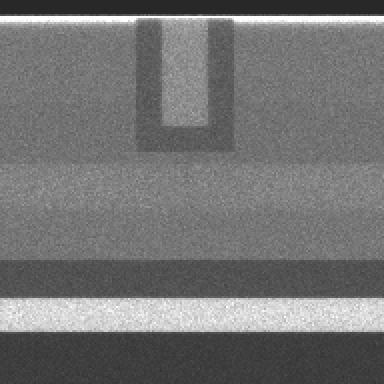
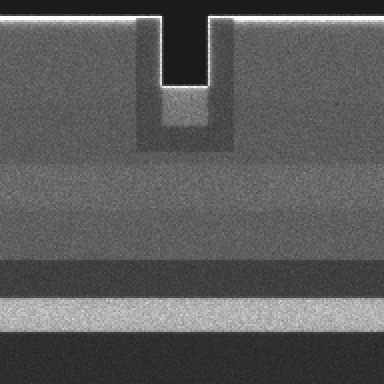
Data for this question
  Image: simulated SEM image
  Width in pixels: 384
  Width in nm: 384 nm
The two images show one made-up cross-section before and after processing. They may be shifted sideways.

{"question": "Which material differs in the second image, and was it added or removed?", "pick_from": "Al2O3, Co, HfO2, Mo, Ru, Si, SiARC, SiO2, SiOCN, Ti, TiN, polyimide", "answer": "Ru, removed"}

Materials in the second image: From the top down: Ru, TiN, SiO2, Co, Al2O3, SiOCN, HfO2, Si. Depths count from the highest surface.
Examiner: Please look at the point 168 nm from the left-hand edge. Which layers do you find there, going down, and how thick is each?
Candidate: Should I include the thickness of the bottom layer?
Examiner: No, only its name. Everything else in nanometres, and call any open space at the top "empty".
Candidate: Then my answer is empty 70, Ru 40, TiN 26, SiO2 12, Co 46, Al2O3 50, SiOCN 38, HfO2 34, Si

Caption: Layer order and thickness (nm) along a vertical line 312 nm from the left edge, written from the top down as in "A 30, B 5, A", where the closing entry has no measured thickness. Al2O3 86, SiO2 62, Co 46, Al2O3 50, SiOCN 38, HfO2 34, Si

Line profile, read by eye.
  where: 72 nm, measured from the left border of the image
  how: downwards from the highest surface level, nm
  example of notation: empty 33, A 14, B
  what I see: Al2O3 86, SiO2 62, Co 46, Al2O3 50, SiOCN 38, HfO2 34, Si